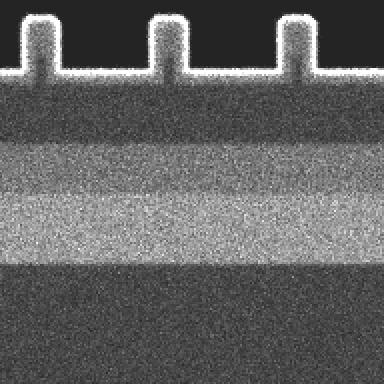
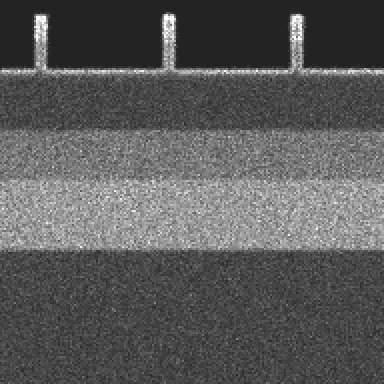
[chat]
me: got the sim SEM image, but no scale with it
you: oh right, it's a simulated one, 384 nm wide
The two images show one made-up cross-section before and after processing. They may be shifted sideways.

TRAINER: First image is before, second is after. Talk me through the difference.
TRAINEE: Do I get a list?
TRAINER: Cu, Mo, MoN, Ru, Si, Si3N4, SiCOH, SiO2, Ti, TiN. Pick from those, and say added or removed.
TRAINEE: removed: Si3N4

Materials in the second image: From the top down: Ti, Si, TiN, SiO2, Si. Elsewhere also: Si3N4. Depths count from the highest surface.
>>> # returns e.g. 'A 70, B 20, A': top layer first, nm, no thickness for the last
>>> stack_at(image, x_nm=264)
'empty 54, Si 60, TiN 50, SiO2 70, Si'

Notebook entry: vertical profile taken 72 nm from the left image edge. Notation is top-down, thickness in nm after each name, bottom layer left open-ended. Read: empty 54, Si 60, TiN 50, SiO2 70, Si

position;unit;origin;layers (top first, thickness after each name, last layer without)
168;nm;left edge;Ti 26, Si 88, TiN 50, SiO2 70, Si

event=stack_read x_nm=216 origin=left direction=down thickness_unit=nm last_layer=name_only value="empty 54, Si 60, TiN 50, SiO2 70, Si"